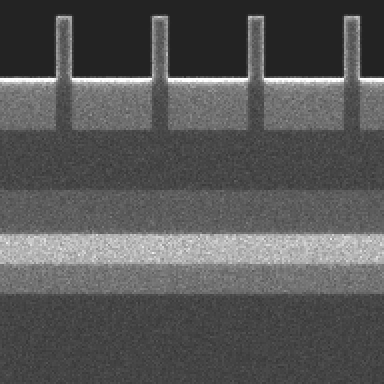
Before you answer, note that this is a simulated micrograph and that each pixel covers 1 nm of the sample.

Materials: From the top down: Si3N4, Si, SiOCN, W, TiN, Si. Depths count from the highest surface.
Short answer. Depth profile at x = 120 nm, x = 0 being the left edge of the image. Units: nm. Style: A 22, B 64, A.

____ empty 62, Si3N4 52, Si 60, SiOCN 44, W 30, TiN 30, Si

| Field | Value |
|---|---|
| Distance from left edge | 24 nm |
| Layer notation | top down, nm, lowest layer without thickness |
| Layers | empty 62, Si3N4 52, Si 60, SiOCN 44, W 30, TiN 30, Si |